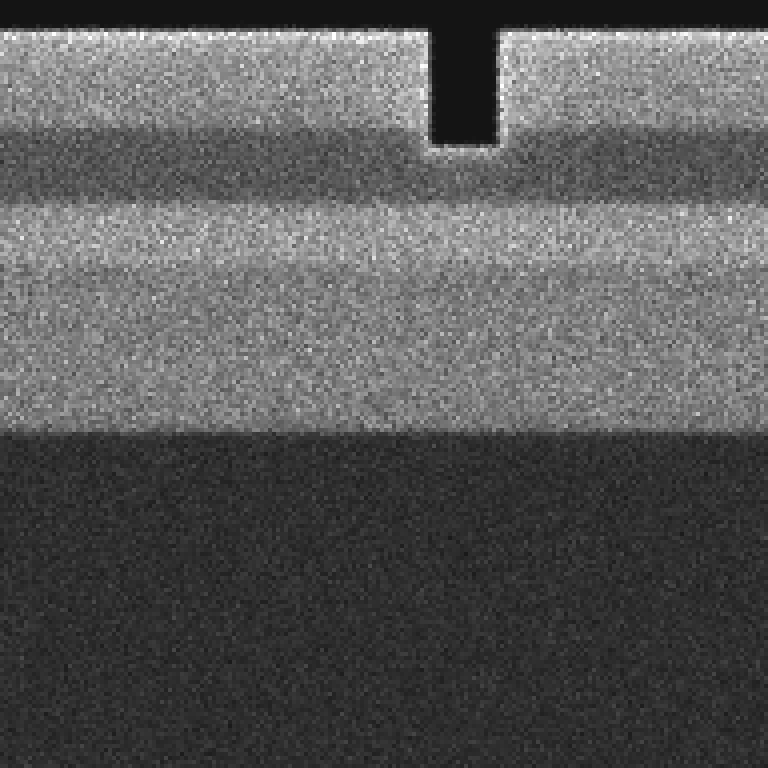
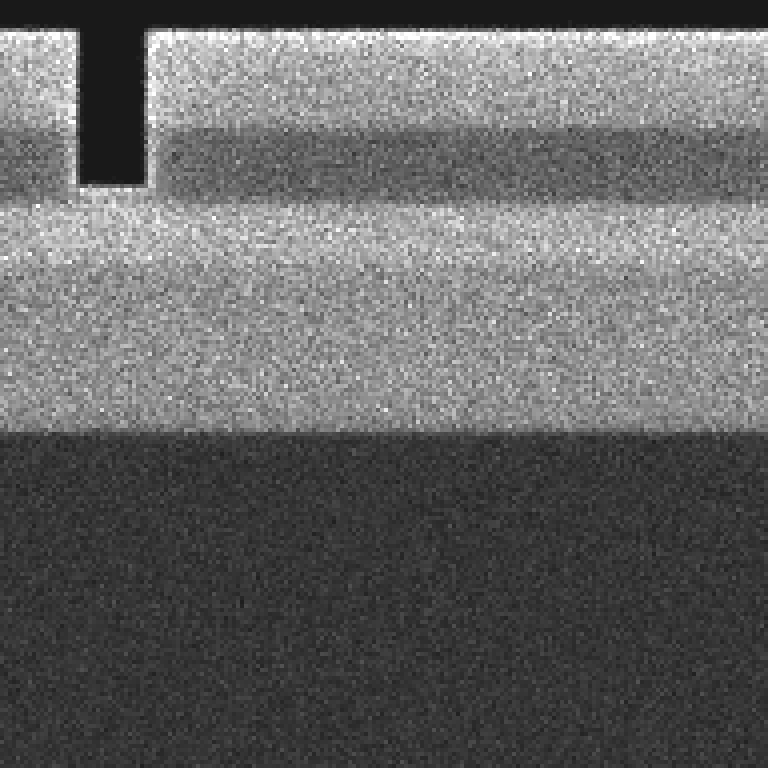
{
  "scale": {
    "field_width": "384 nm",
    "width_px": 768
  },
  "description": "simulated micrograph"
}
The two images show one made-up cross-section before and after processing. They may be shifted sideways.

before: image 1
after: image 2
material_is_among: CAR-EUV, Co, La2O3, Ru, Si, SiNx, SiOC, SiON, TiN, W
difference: TiN, removed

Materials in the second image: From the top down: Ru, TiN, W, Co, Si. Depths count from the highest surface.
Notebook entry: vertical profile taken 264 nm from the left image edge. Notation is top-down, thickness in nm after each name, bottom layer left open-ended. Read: Ru 48, TiN 38, W 30, Co 84, Si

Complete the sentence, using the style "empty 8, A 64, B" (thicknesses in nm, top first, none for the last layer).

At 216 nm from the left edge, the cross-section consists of Ru 48, TiN 38, W 30, Co 84, Si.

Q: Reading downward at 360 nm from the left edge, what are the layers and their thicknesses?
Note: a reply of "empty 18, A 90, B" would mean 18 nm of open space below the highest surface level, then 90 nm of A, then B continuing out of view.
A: Ru 48, TiN 38, W 30, Co 84, Si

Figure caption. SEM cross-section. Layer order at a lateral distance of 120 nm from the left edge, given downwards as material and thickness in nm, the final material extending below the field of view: Ru 48, TiN 38, W 30, Co 84, Si